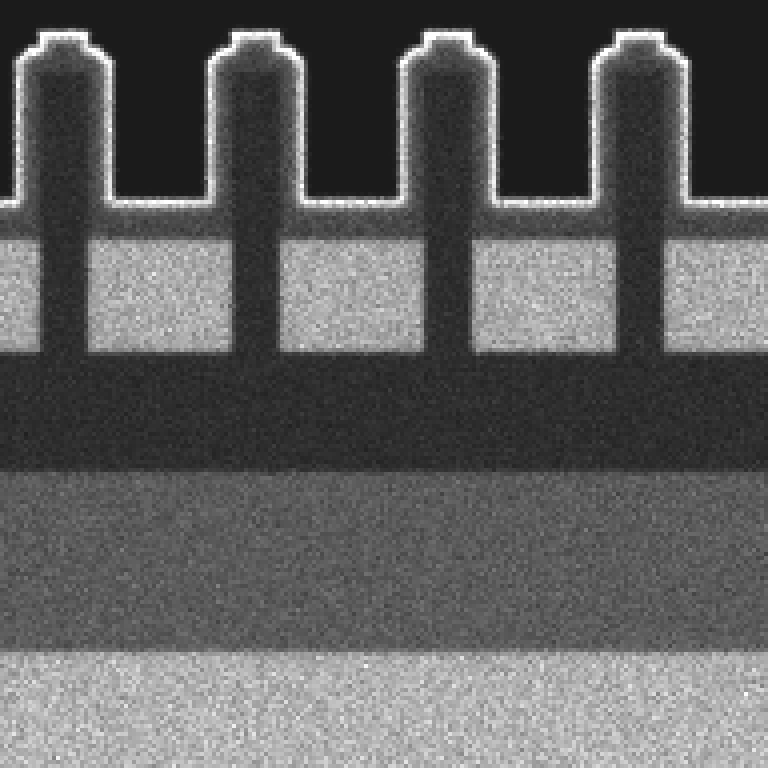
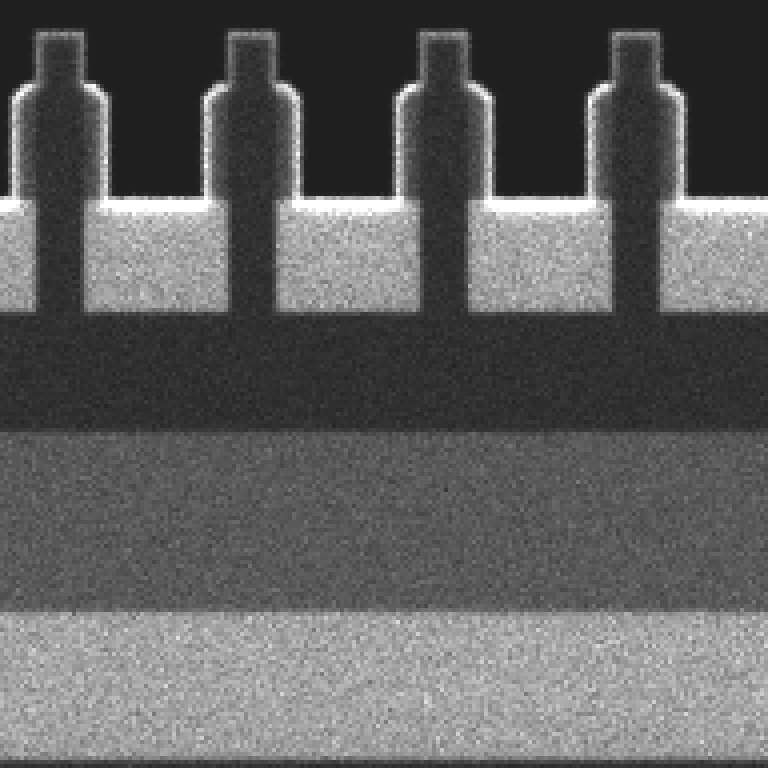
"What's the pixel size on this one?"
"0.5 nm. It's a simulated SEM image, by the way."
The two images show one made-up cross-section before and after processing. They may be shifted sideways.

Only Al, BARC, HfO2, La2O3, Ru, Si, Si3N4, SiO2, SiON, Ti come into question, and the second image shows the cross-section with Si3N4 removed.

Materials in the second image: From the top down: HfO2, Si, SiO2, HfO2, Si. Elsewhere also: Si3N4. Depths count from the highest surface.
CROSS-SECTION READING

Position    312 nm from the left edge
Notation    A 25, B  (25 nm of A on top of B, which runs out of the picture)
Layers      Si 200, SiO2 90, HfO2 74, Si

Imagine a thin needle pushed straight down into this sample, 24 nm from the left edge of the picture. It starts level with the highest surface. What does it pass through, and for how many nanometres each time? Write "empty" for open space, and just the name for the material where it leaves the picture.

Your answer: Si 200, SiO2 90, HfO2 74, Si